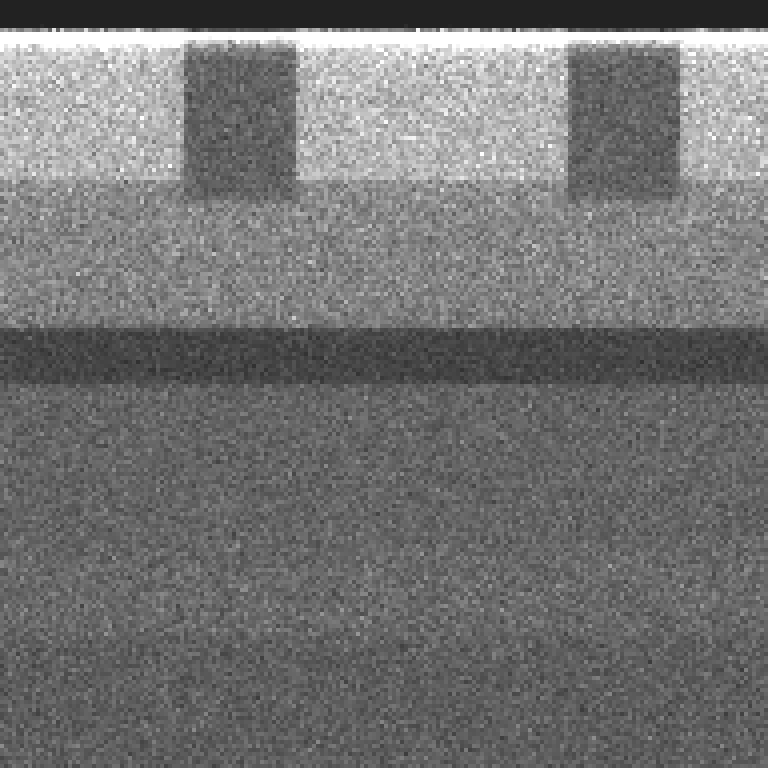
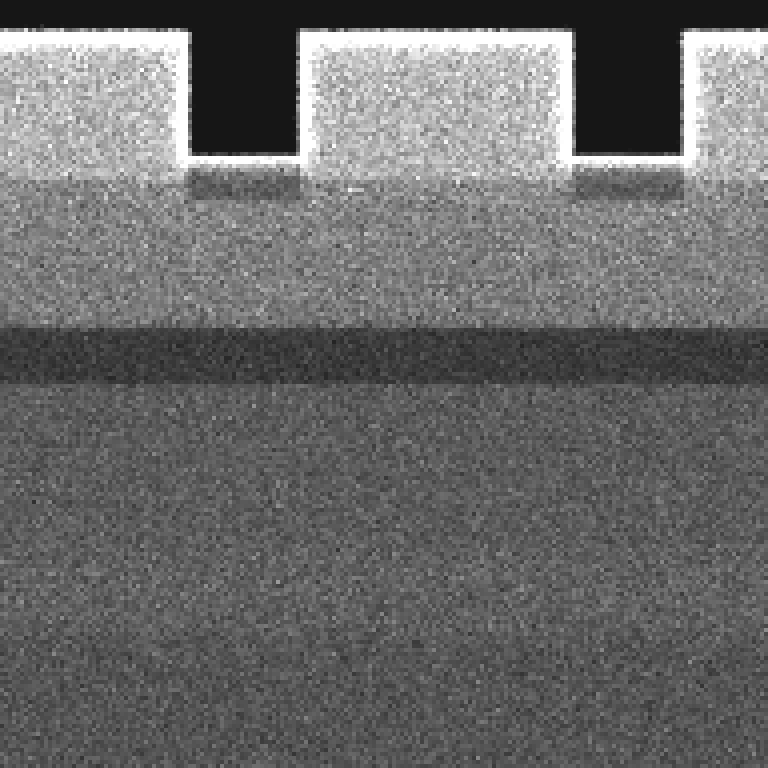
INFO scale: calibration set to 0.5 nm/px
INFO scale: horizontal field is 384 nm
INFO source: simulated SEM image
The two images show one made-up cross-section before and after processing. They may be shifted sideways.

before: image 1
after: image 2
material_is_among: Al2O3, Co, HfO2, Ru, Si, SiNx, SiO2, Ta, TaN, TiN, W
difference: SiO2, removed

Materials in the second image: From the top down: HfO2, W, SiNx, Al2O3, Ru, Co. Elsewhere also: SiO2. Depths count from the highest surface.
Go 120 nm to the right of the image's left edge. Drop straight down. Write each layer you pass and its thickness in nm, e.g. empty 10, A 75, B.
empty 62, SiO2 22, W 64, SiNx 28, Al2O3 82, Ru 44, Co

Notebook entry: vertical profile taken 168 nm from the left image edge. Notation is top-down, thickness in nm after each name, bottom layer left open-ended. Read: HfO2 74, W 74, SiNx 28, Al2O3 82, Ru 44, Co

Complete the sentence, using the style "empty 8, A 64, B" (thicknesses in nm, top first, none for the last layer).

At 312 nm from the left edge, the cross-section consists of empty 62, SiO2 22, W 64, SiNx 28, Al2O3 82, Ru 44, Co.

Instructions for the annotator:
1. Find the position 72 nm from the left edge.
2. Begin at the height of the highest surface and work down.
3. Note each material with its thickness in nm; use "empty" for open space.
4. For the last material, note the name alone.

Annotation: HfO2 74, W 74, SiNx 28, Al2O3 82, Ru 44, Co